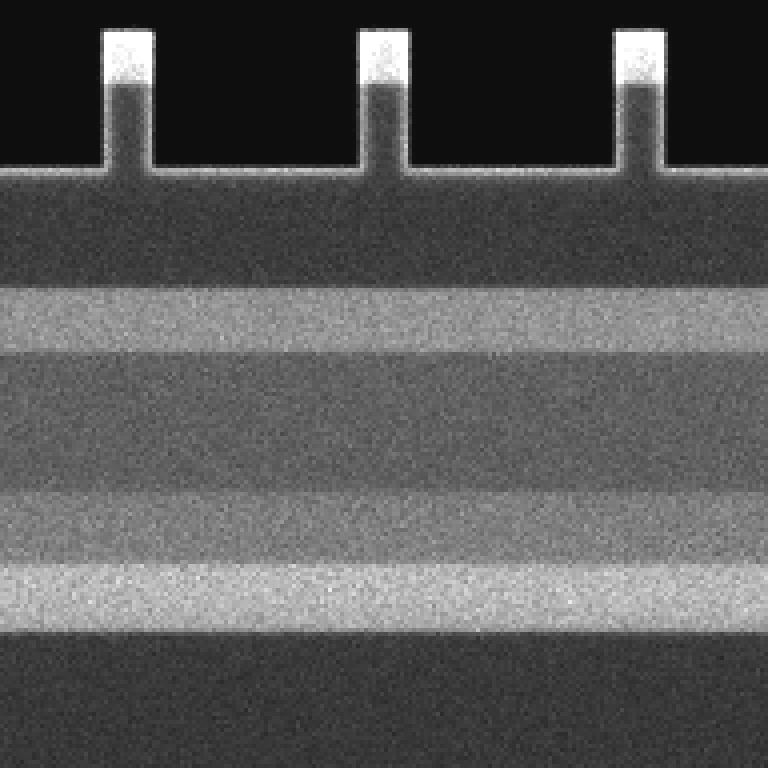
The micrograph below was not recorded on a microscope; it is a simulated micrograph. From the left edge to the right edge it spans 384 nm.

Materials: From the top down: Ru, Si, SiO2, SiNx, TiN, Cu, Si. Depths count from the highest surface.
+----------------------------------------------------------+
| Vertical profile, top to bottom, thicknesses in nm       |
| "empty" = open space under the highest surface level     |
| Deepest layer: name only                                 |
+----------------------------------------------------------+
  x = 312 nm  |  Ru 26, Si 102, SiO2 32, SiNx 70, TiN 36, Cu 34, Si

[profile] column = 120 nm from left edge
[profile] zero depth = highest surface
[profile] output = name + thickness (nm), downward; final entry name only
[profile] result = empty 68, Si 60, SiO2 32, SiNx 70, TiN 36, Cu 34, Si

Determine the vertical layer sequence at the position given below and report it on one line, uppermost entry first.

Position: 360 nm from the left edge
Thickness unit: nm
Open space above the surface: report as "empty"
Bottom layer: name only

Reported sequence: empty 68, Si 60, SiO2 32, SiNx 70, TiN 36, Cu 34, Si